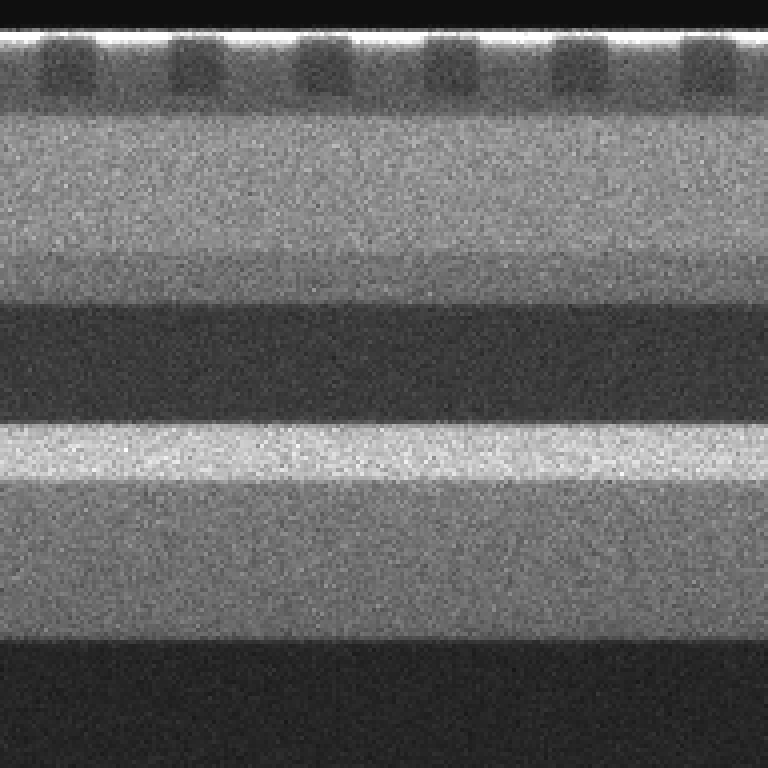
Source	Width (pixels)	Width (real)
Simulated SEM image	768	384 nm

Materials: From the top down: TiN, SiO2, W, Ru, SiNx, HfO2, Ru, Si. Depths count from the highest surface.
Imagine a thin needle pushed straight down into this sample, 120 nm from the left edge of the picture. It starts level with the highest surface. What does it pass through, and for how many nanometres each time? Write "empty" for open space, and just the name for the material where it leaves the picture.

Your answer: SiO2 42, W 68, Ru 26, SiNx 60, HfO2 28, Ru 80, Si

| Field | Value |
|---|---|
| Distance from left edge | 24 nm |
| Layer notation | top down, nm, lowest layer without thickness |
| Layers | TiN 32, SiO2 10, W 68, Ru 26, SiNx 60, HfO2 28, Ru 80, Si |